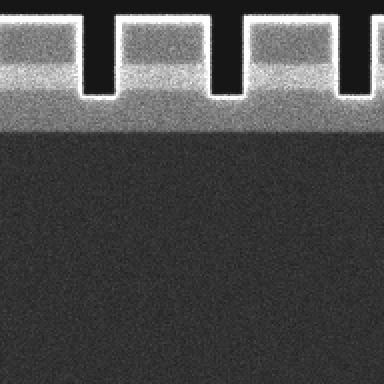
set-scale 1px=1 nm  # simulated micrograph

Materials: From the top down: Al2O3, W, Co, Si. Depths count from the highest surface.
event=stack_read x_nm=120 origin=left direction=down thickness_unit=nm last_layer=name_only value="Al2O3 48, W 26, Co 42, Si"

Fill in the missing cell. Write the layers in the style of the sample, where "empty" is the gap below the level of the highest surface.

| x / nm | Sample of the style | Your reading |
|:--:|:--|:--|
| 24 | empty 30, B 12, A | Al2O3 48, W 26, Co 42, Si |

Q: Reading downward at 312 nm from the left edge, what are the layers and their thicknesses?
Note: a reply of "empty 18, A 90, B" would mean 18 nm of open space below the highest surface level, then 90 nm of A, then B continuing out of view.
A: Al2O3 48, W 26, Co 42, Si